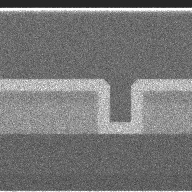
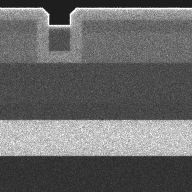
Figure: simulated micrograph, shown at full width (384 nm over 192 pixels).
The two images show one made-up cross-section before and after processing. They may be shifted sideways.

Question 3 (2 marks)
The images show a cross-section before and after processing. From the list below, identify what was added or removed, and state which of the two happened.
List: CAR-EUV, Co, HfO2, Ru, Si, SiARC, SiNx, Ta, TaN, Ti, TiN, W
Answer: SiARC was removed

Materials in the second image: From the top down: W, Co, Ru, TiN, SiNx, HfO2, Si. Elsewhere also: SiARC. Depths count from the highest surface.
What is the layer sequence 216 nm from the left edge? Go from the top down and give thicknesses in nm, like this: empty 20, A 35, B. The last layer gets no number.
W 24, Co 24, Ru 62, TiN 80, SiNx 34, HfO2 72, Si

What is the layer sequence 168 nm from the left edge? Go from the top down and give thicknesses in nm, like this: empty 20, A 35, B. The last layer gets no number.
W 24, Co 24, Ru 62, TiN 80, SiNx 34, HfO2 72, Si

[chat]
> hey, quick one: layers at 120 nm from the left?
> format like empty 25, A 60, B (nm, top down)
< empty 34, SiARC 52, W 24, TiN 80, SiNx 34, HfO2 72, Si